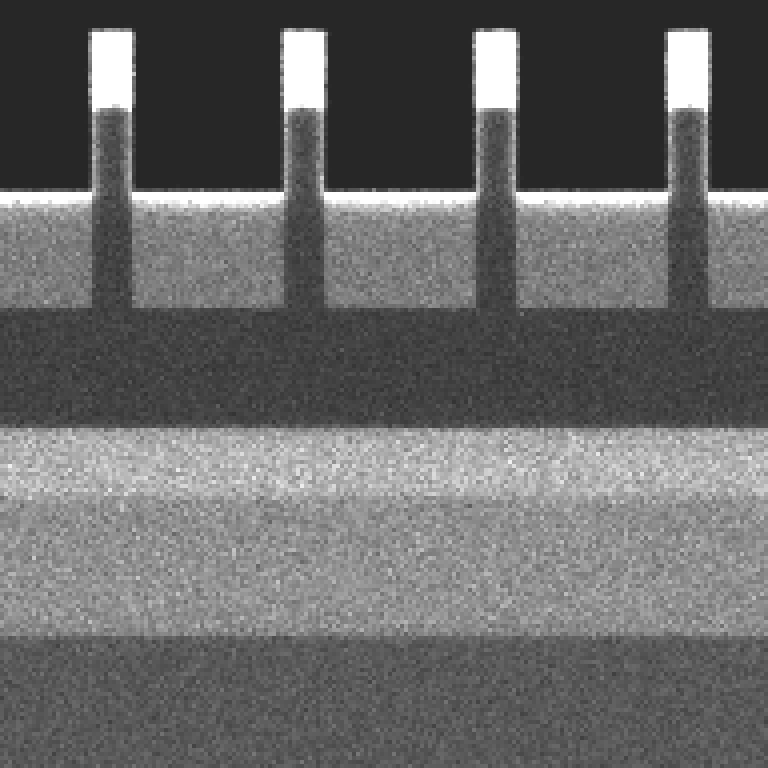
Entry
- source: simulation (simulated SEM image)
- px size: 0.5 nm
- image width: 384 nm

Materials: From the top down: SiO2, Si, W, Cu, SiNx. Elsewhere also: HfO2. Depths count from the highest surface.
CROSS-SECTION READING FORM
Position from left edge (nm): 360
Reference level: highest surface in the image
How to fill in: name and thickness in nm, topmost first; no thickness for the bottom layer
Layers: empty 80, SiO2 58, Si 60, W 34, Cu 70, SiNx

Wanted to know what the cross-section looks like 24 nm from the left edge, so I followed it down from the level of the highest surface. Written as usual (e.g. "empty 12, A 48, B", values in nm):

empty 80, SiO2 58, Si 60, W 34, Cu 70, SiNx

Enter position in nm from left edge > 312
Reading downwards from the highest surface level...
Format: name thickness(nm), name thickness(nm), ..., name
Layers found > empty 80, SiO2 58, Si 60, W 34, Cu 70, SiNx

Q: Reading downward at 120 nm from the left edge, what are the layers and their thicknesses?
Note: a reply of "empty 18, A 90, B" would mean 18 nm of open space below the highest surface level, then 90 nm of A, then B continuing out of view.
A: empty 80, SiO2 58, Si 60, W 34, Cu 70, SiNx